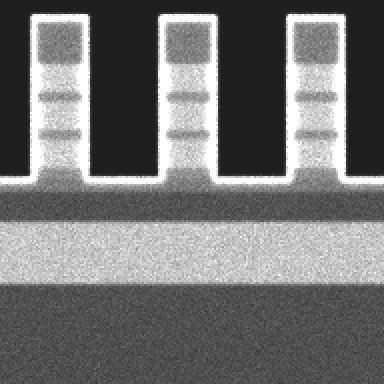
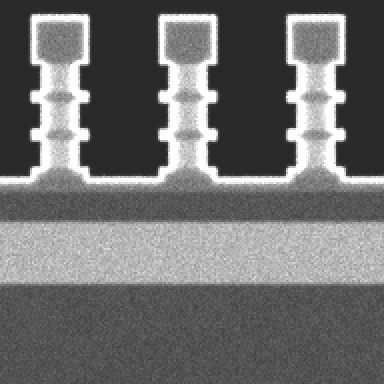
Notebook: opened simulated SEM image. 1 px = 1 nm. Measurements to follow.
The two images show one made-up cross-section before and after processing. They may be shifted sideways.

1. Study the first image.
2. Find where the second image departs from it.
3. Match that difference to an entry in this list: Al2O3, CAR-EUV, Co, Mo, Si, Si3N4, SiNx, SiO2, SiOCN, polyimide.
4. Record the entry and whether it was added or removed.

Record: Al2O3 / removed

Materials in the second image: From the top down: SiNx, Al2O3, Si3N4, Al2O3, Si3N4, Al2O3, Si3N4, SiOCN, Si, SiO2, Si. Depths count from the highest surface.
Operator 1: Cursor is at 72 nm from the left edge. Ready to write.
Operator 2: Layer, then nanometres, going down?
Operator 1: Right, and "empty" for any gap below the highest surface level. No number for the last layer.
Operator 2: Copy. SiNx 48, Al2O3 28, Si3N4 10, Al2O3 28, Si3N4 10, Al2O3 28, Si3N4 10, SiOCN 14, Si 30, SiO2 62, Si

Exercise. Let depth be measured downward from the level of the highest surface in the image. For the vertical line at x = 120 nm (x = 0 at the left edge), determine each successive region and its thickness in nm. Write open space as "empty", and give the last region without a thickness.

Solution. empty 162, SiOCN 14, Si 30, SiO2 62, Si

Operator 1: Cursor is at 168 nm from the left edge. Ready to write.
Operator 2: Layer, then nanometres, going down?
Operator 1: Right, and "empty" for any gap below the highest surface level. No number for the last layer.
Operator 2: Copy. SiNx 48, empty 28, Si3N4 10, empty 28, Si3N4 10, empty 28, Si3N4 10, SiOCN 14, Si 30, SiO2 62, Si